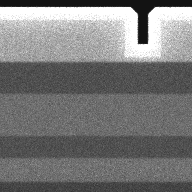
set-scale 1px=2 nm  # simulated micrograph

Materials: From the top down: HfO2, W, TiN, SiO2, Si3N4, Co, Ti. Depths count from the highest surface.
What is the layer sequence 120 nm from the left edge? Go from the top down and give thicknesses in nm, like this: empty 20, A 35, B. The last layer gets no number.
HfO2 24, W 84, TiN 64, SiO2 84, Si3N4 44, Co 48, Ti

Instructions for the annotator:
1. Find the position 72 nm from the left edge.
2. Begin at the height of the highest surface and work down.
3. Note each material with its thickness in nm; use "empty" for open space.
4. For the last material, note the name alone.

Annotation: HfO2 24, W 84, TiN 64, SiO2 84, Si3N4 44, Co 48, Ti